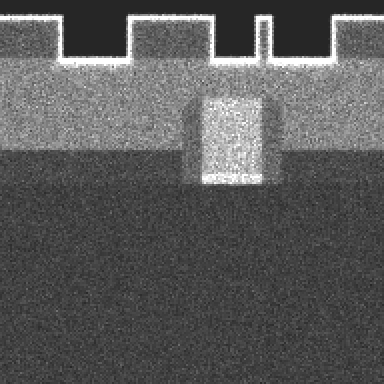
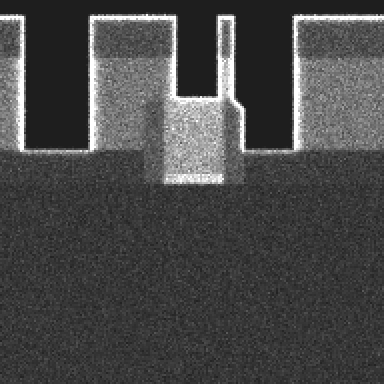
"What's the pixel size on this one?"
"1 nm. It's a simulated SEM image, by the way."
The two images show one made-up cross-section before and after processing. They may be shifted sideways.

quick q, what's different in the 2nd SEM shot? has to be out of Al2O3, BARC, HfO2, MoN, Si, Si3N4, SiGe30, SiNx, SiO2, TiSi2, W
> SiO2 removed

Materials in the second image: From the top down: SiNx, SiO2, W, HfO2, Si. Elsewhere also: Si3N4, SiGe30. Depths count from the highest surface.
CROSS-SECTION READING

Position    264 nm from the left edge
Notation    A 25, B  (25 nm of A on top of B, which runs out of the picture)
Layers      empty 134, SiGe30 34, Si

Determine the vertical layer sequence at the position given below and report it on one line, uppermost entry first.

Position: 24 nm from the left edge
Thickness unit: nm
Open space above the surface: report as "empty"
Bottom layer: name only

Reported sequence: empty 134, SiGe30 34, Si